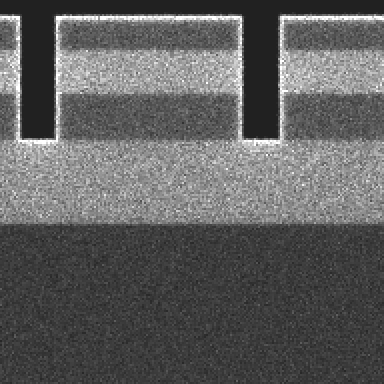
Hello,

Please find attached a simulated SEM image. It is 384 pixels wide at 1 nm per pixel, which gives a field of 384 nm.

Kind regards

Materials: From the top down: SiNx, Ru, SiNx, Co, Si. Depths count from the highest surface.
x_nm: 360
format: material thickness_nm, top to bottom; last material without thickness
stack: SiNx 34, Ru 44, SiNx 46, Co 84, Si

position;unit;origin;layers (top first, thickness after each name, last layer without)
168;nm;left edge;SiNx 34, Ru 44, SiNx 46, Co 84, Si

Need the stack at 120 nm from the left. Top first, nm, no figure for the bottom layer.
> SiNx 34, Ru 44, SiNx 46, Co 84, Si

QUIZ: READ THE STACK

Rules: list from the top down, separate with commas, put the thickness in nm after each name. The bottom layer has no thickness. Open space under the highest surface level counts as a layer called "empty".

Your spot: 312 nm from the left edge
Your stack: SiNx 34, Ru 44, SiNx 46, Co 84, Si